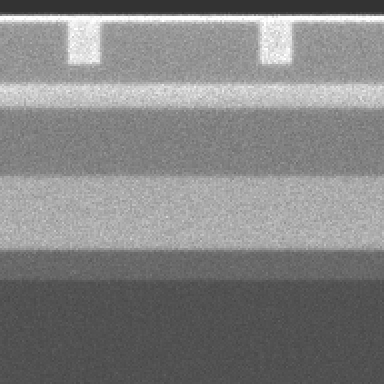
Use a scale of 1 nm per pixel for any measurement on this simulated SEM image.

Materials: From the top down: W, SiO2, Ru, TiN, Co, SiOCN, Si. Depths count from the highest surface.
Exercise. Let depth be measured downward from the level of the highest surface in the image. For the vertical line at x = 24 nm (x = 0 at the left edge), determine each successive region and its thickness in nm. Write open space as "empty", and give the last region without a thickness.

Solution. W 6, SiO2 62, Ru 24, TiN 68, Co 74, SiOCN 30, Si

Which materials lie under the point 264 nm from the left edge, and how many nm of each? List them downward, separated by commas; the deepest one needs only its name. W 48, SiO2 20, Ru 24, TiN 68, Co 74, SiOCN 30, Si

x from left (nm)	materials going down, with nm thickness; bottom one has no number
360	W 6, SiO2 62, Ru 24, TiN 68, Co 74, SiOCN 30, Si